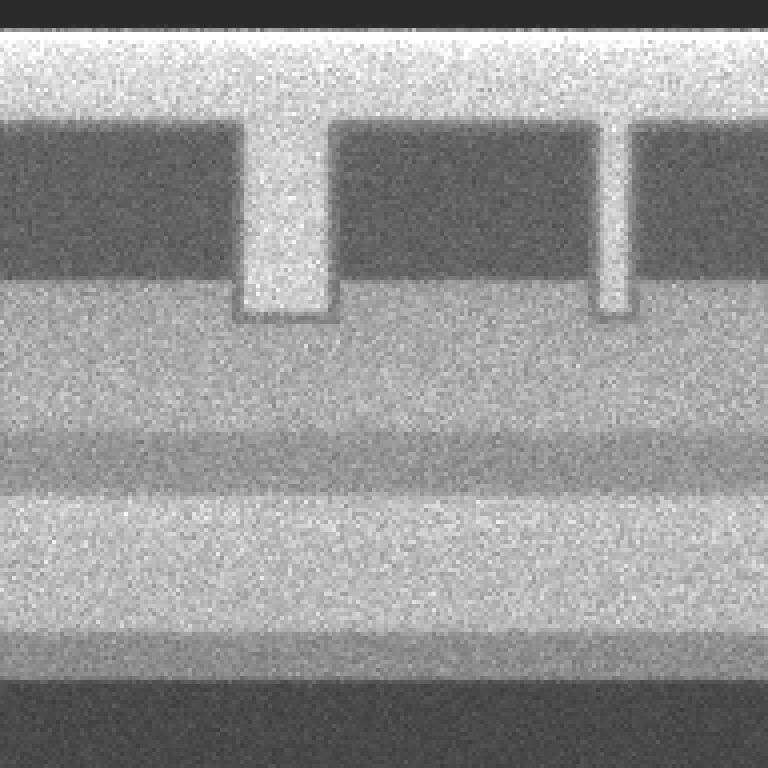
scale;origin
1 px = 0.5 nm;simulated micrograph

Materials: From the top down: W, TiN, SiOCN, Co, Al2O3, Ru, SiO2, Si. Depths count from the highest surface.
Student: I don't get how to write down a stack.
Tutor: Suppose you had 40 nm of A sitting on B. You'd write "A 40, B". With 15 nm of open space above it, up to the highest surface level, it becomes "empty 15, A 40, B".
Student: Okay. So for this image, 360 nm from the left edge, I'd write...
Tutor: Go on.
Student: W 44, TiN 6, SiOCN 74, Co 76, Al2O3 32, Ru 68, SiO2 24, Si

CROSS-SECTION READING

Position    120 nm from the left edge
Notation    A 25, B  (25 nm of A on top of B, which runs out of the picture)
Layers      W 46, TiN 100, Co 54, Al2O3 32, Ru 68, SiO2 24, Si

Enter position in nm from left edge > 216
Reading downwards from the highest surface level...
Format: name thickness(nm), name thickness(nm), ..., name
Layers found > W 44, TiN 6, SiOCN 74, Co 76, Al2O3 32, Ru 68, SiO2 24, Si